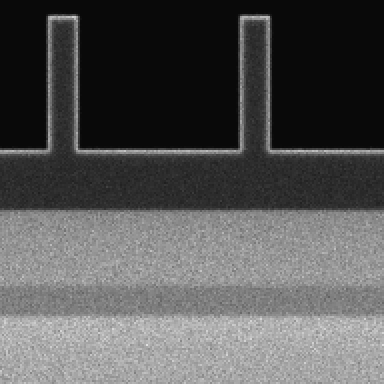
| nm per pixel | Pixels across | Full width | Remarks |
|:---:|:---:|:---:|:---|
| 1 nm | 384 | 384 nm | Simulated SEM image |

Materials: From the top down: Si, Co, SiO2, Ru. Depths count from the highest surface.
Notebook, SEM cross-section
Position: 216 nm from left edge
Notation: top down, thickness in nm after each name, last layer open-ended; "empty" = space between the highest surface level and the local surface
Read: empty 134, Si 60, Co 76, SiO2 30, Ru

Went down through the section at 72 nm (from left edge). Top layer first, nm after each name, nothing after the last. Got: Si 194, Co 76, SiO2 30, Ru